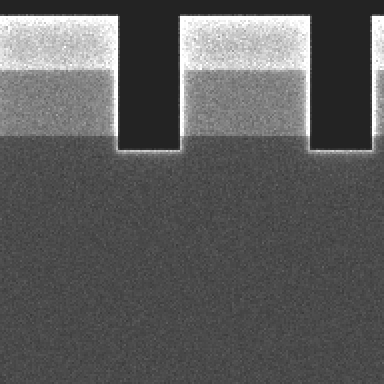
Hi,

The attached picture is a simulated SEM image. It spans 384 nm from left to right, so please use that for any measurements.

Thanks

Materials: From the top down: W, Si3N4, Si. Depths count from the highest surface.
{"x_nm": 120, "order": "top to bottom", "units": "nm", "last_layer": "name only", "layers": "empty 134, Si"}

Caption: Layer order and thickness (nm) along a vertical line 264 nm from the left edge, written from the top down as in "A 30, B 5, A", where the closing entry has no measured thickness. W 54, Si3N4 66, Si